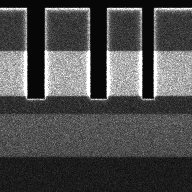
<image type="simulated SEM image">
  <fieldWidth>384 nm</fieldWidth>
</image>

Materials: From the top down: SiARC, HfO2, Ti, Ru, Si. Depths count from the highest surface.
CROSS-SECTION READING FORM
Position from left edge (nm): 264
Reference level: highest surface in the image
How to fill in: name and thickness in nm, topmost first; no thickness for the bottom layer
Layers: SiARC 86, HfO2 90, Ti 36, Ru 86, Si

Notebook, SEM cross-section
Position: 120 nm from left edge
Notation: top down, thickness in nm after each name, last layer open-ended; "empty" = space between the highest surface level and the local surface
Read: SiARC 86, HfO2 90, Ti 36, Ru 86, Si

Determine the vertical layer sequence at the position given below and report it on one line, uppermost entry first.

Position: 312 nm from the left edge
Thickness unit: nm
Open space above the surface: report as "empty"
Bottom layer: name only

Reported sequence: SiARC 86, HfO2 90, Ti 36, Ru 86, Si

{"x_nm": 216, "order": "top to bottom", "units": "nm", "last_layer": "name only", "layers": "SiARC 86, HfO2 90, Ti 36, Ru 86, Si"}